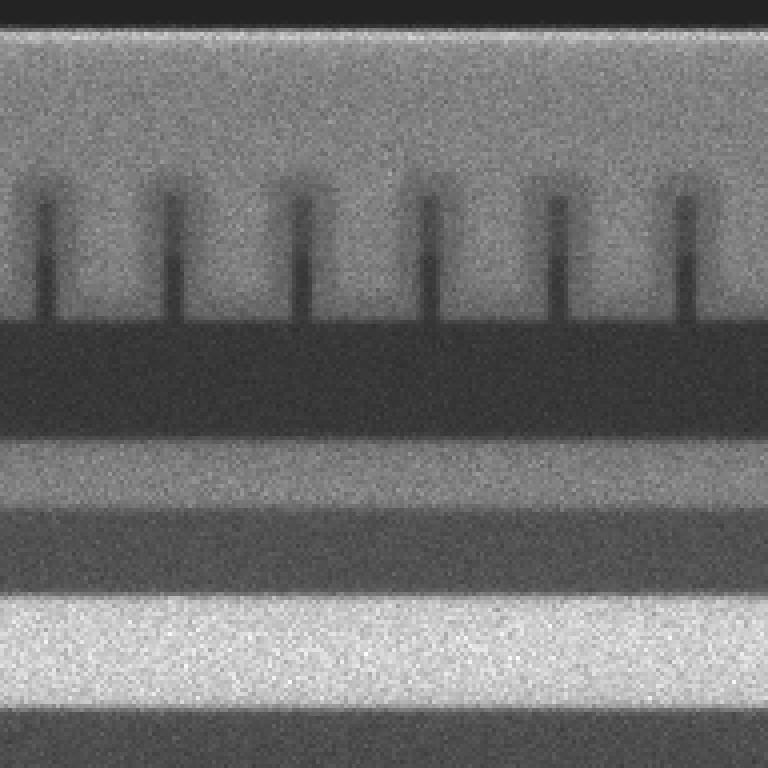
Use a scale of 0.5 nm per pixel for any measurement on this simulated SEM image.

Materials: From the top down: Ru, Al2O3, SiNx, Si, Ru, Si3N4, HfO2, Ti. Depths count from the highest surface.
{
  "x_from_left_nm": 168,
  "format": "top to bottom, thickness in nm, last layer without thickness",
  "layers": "Ru 132, Al2O3 12, Si 60, Ru 34, Si3N4 44, HfO2 56, Ti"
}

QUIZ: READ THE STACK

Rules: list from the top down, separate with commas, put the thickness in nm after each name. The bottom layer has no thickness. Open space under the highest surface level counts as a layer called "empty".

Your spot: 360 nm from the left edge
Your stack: Ru 132, Al2O3 12, Si 60, Ru 34, Si3N4 44, HfO2 56, Ti